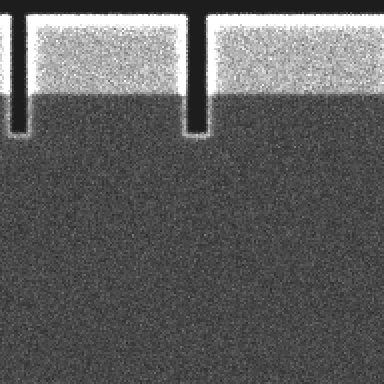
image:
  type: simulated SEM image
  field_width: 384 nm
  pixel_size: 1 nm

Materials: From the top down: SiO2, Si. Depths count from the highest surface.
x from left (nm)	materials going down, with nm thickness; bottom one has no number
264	SiO2 78, Si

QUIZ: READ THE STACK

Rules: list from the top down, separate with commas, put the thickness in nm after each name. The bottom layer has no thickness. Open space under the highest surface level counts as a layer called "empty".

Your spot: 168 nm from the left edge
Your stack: SiO2 78, Si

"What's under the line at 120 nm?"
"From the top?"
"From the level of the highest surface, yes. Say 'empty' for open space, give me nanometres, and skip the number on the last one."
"SiO2 78, Si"